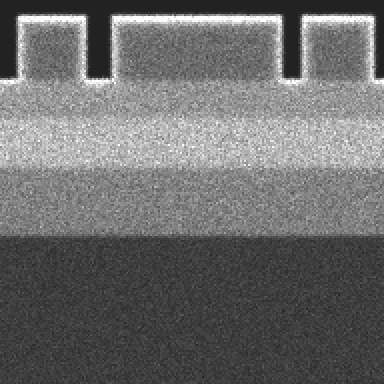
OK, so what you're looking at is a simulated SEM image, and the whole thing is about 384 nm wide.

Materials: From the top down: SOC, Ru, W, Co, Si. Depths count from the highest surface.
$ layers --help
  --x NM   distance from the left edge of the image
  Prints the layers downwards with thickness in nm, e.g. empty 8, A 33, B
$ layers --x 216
SOC 64, Ru 38, W 50, Co 68, Si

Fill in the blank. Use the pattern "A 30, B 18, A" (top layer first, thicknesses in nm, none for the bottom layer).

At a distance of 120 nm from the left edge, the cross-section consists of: SOC 64, Ru 38, W 50, Co 68, Si